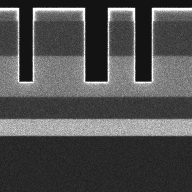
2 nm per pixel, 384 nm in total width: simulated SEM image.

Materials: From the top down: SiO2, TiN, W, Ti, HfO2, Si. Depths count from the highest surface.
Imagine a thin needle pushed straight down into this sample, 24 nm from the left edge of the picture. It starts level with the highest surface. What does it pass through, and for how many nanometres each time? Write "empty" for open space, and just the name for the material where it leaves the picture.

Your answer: SiO2 26, TiN 70, W 82, Ti 44, HfO2 34, Si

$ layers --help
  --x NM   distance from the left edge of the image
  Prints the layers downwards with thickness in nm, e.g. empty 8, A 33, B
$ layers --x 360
SiO2 26, TiN 70, W 82, Ti 44, HfO2 34, Si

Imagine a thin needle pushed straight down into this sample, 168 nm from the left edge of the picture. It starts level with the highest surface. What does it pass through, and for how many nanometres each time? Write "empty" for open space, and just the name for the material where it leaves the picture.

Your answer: SiO2 26, TiN 70, W 82, Ti 44, HfO2 34, Si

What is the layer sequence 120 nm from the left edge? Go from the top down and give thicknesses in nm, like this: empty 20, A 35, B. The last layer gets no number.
SiO2 26, TiN 70, W 82, Ti 44, HfO2 34, Si